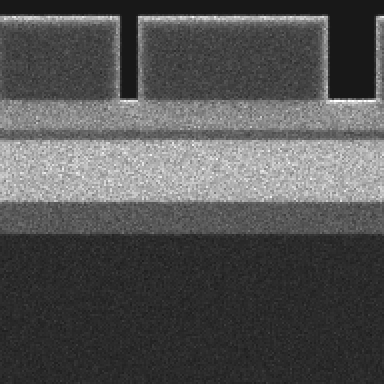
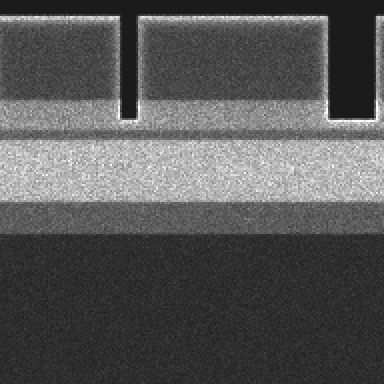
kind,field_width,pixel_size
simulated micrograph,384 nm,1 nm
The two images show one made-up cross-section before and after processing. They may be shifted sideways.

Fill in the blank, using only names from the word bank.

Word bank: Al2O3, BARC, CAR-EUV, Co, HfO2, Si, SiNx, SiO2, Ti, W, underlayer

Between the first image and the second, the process removed W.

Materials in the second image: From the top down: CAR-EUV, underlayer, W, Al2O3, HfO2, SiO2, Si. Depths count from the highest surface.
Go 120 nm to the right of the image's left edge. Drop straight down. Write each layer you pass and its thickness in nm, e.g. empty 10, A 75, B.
empty 104, W 10, Al2O3 10, HfO2 62, SiO2 32, Si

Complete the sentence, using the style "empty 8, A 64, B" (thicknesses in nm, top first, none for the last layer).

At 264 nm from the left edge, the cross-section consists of CAR-EUV 66, underlayer 18, W 30, Al2O3 10, HfO2 62, SiO2 32, Si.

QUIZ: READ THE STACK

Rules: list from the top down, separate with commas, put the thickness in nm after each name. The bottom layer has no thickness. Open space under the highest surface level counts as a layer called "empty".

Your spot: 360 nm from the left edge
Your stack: empty 104, W 10, Al2O3 10, HfO2 62, SiO2 32, Si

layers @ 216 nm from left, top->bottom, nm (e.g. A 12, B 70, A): CAR-EUV 66, underlayer 18, W 30, Al2O3 10, HfO2 62, SiO2 32, Si